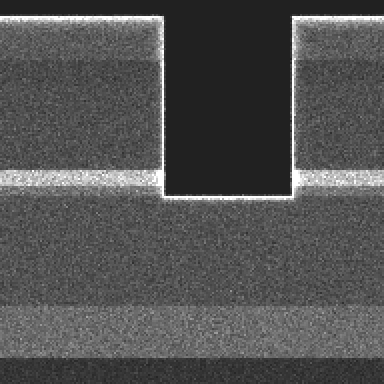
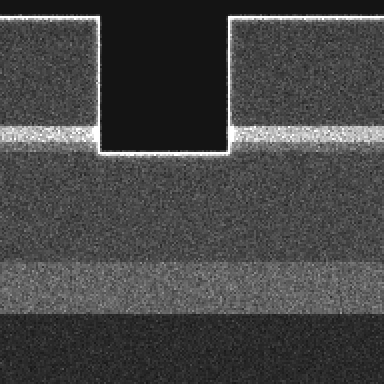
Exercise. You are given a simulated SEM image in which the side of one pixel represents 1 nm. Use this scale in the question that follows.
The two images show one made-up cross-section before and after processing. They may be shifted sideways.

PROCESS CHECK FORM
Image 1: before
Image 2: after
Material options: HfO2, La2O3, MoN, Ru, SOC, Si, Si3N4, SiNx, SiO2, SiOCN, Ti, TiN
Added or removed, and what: removed, SOC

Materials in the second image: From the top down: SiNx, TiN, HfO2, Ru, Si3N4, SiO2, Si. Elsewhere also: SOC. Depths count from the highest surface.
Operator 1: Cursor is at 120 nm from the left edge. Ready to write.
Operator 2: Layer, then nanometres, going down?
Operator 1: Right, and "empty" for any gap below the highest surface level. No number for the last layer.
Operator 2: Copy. empty 136, Si3N4 110, SiO2 52, Si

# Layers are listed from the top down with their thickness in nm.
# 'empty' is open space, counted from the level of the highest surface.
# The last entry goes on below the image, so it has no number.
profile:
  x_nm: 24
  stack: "SiNx 24, TiN 86, HfO2 16, Ru 10, Si3N4 110, SiO2 52, Si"